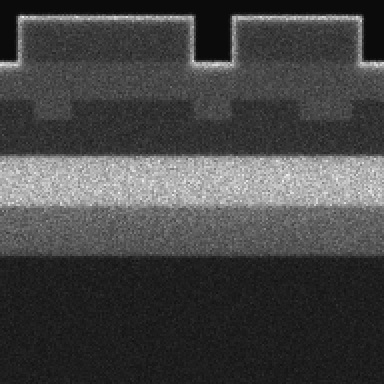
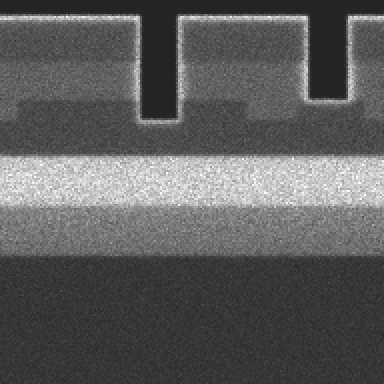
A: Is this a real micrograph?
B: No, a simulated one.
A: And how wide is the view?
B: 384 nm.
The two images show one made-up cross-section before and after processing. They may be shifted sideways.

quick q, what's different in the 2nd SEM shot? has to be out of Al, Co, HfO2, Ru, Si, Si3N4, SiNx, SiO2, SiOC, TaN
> SiO2 removed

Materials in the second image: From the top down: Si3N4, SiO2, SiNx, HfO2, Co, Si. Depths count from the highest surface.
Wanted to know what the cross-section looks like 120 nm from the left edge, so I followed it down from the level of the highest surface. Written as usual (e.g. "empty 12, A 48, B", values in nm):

Si3N4 46, SiO2 38, SiNx 56, HfO2 50, Co 50, Si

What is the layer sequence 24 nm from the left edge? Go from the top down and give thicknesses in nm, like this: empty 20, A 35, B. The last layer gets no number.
Si3N4 46, SiO2 38, SiNx 56, HfO2 50, Co 50, Si